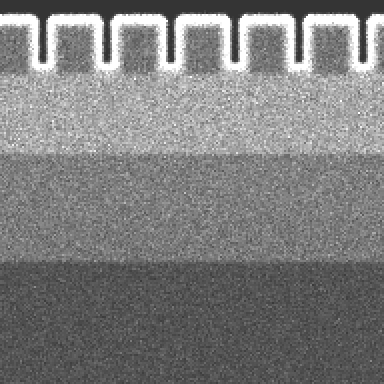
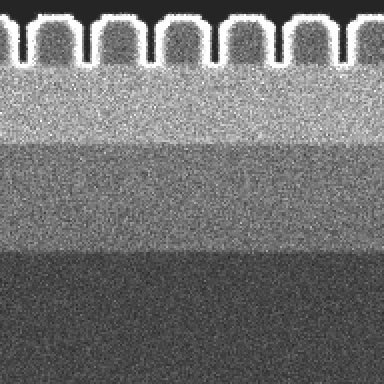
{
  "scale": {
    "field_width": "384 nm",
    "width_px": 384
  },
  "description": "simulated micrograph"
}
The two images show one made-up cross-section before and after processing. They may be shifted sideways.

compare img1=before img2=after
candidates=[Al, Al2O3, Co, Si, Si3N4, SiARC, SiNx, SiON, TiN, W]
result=removed:Al2O3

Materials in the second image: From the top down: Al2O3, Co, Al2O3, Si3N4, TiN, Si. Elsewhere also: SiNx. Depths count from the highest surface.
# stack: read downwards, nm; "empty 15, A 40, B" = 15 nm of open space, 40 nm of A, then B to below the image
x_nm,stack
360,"SiNx 48, Co 28, Al2O3 52, Si3N4 64, TiN 44, Si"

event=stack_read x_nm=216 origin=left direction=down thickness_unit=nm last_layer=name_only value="empty 48, Co 28, Al2O3 52, Si3N4 64, TiN 44, Si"